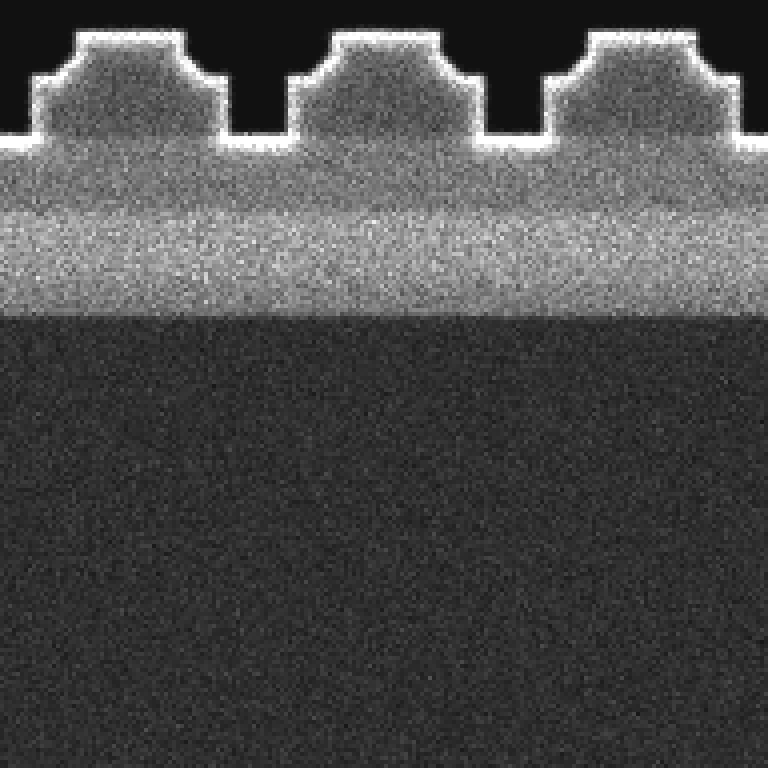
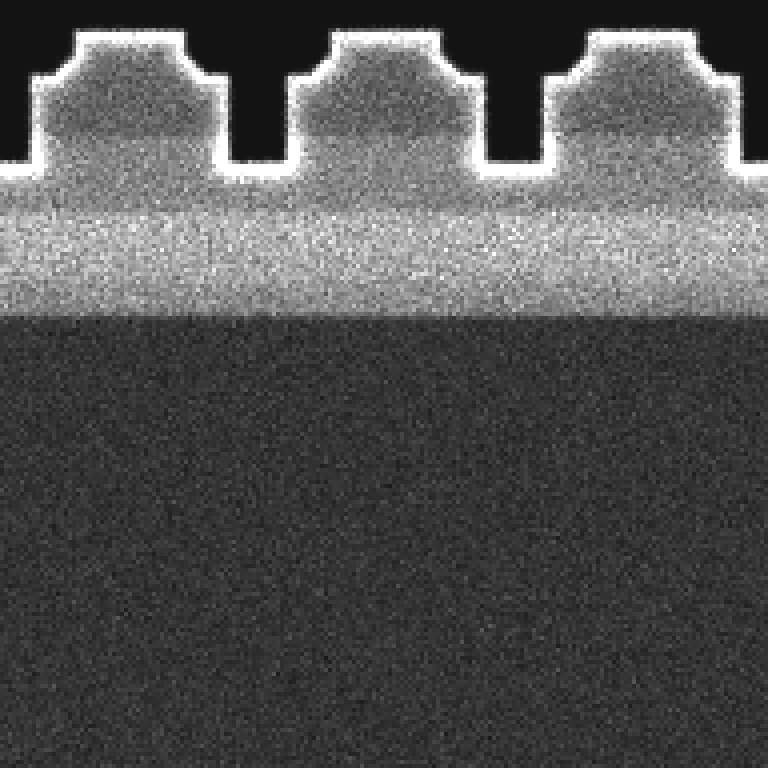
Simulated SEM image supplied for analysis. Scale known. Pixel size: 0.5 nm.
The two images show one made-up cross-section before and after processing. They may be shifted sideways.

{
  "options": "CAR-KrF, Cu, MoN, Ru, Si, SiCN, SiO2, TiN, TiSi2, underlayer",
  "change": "removed",
  "material": "SiO2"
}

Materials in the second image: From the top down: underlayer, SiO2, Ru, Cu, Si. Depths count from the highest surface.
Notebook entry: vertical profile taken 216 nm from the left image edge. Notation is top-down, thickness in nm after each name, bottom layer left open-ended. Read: underlayer 52, SiO2 38, Ru 36, Cu 16, Si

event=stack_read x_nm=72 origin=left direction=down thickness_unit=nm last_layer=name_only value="underlayer 52, SiO2 38, Ru 36, Cu 16, Si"